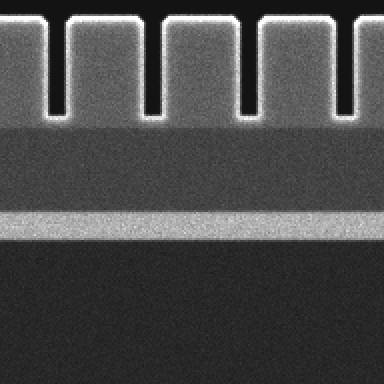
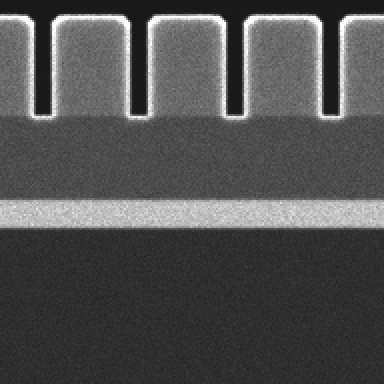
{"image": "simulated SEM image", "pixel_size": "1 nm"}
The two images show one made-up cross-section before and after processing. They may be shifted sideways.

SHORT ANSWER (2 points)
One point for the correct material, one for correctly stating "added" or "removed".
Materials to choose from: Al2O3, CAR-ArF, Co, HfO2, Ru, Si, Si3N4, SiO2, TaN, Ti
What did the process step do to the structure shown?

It removed SiO2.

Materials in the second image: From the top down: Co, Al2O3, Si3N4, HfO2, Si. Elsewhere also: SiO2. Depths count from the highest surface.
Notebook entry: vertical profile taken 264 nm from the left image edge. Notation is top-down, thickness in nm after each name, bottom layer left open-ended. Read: Co 52, Al2O3 48, Si3N4 84, HfO2 28, Si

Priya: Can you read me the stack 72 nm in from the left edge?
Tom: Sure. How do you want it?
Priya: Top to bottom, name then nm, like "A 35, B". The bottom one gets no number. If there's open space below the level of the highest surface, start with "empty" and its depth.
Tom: Co 52, Al2O3 48, Si3N4 84, HfO2 28, Si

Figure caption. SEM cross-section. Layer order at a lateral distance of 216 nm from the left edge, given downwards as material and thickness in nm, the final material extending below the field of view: SiO2 100, Si3N4 84, HfO2 28, Si